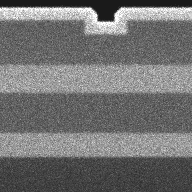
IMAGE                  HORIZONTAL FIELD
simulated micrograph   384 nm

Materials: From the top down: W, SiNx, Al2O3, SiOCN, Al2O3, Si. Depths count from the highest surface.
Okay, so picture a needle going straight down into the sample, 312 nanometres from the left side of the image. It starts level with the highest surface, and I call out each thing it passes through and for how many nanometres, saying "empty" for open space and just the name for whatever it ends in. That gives W 24, SiNx 90, Al2O3 56, SiOCN 80, Al2O3 48, Si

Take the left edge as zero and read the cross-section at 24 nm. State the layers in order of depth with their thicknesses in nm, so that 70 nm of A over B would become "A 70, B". W 24, SiNx 90, Al2O3 56, SiOCN 80, Al2O3 48, Si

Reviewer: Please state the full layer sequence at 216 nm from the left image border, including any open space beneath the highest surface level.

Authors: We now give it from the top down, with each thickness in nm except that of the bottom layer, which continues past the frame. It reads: empty 28, W 24, SiNx 62, Al2O3 56, SiOCN 80, Al2O3 48, Si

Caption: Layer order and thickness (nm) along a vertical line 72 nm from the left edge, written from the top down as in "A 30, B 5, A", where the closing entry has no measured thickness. W 24, SiNx 90, Al2O3 56, SiOCN 80, Al2O3 48, Si